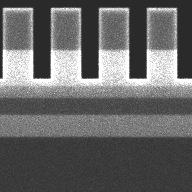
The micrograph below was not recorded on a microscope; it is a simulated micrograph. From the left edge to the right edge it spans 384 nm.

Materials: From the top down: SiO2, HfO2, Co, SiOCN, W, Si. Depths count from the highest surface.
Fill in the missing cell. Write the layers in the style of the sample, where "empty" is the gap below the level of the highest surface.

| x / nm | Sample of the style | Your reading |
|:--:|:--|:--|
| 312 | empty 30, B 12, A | SiO2 84, HfO2 72, Co 24, SiOCN 34, W 44, Si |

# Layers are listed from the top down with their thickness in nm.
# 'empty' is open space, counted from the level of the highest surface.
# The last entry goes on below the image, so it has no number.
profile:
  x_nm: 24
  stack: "SiO2 84, HfO2 72, Co 24, SiOCN 34, W 44, Si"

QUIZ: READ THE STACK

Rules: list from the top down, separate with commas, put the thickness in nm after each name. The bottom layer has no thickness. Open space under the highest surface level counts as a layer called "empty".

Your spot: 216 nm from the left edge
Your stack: SiO2 84, HfO2 72, Co 24, SiOCN 34, W 44, Si